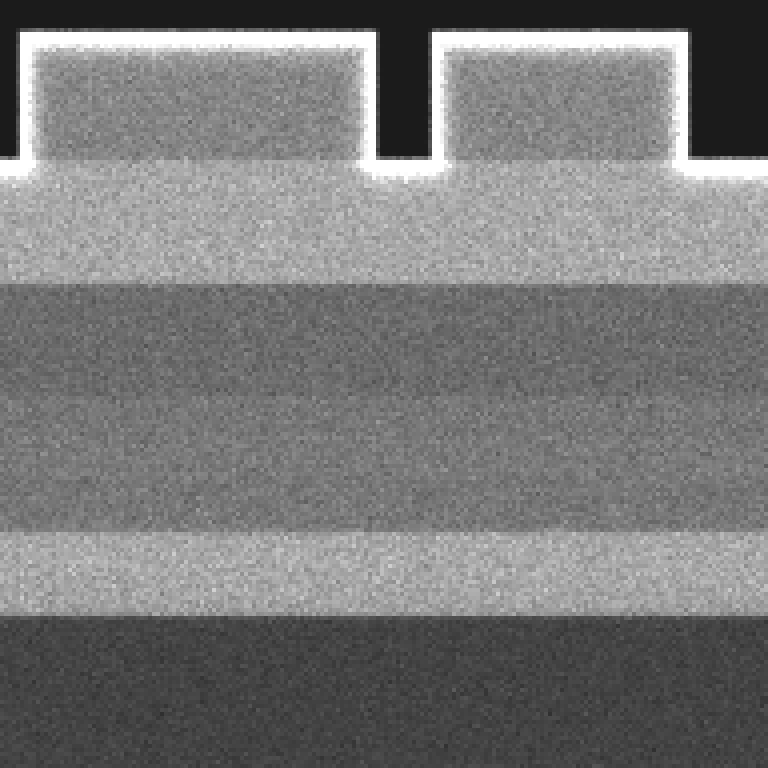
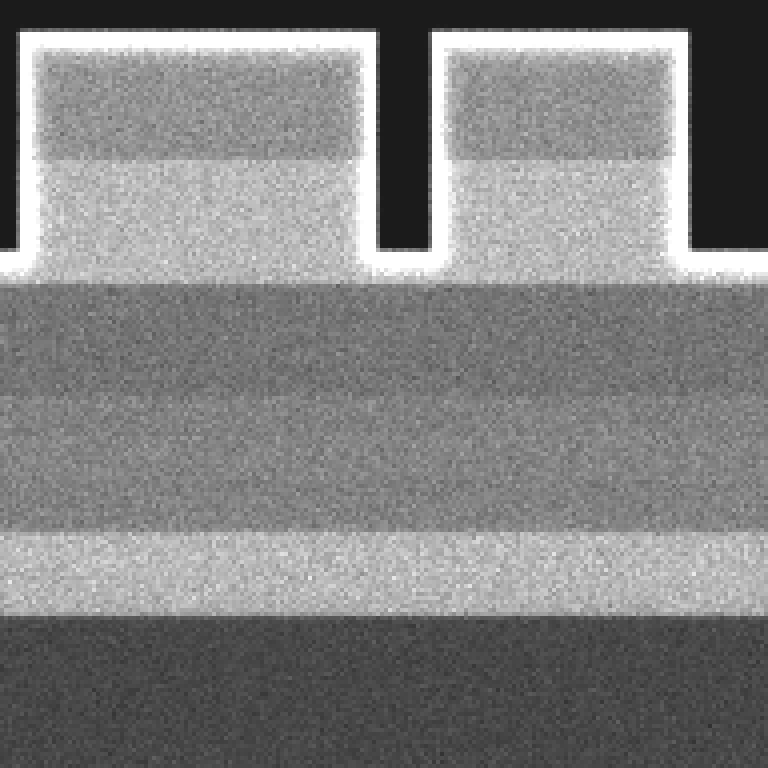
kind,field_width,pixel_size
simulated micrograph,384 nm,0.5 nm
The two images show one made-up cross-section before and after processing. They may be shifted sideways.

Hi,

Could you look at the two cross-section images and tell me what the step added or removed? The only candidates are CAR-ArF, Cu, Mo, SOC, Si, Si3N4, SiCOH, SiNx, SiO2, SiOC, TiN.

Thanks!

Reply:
removed SiO2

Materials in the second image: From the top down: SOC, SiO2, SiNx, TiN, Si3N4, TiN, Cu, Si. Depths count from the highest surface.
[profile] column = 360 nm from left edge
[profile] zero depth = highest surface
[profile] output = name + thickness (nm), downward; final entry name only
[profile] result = empty 110, SiO2 16, SiNx 56, TiN 20, Si3N4 22, TiN 26, Cu 42, Si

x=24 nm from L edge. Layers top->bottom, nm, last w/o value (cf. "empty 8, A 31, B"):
SOC 64, SiO2 62, SiNx 56, TiN 20, Si3N4 22, TiN 26, Cu 42, Si